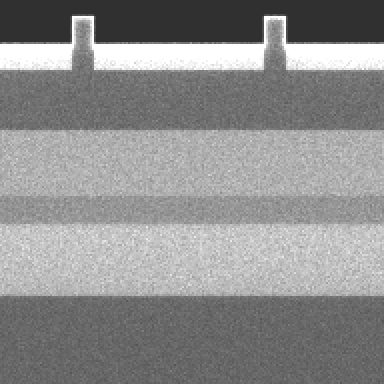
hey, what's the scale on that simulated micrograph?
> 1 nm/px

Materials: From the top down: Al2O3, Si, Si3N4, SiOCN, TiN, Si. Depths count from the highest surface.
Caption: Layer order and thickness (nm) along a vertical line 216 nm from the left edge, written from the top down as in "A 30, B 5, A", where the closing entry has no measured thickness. empty 28, Al2O3 26, Si 60, Si3N4 66, SiOCN 28, TiN 72, Si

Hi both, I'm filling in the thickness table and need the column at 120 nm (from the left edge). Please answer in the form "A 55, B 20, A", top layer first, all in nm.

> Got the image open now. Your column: empty 28, Al2O3 26, Si 60, Si3N4 66, SiOCN 28, TiN 72, Si